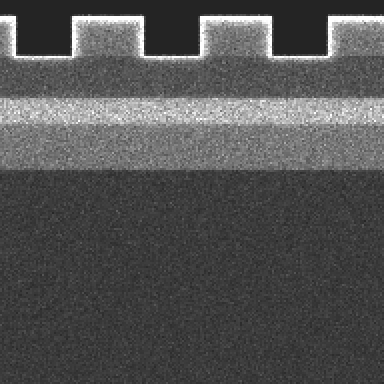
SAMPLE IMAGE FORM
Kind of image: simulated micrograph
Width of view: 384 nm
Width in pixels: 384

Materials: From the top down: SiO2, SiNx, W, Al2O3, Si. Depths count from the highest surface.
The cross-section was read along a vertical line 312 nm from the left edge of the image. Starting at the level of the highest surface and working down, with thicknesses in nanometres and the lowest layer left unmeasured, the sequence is empty 40, SiNx 42, W 26, Al2O3 46, Si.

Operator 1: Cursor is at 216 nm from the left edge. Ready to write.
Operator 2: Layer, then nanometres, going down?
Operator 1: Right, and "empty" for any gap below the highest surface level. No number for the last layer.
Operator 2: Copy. SiO2 40, SiNx 42, W 26, Al2O3 46, Si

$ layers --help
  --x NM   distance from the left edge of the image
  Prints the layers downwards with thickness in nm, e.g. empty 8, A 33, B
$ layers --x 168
empty 40, SiNx 42, W 26, Al2O3 46, Si